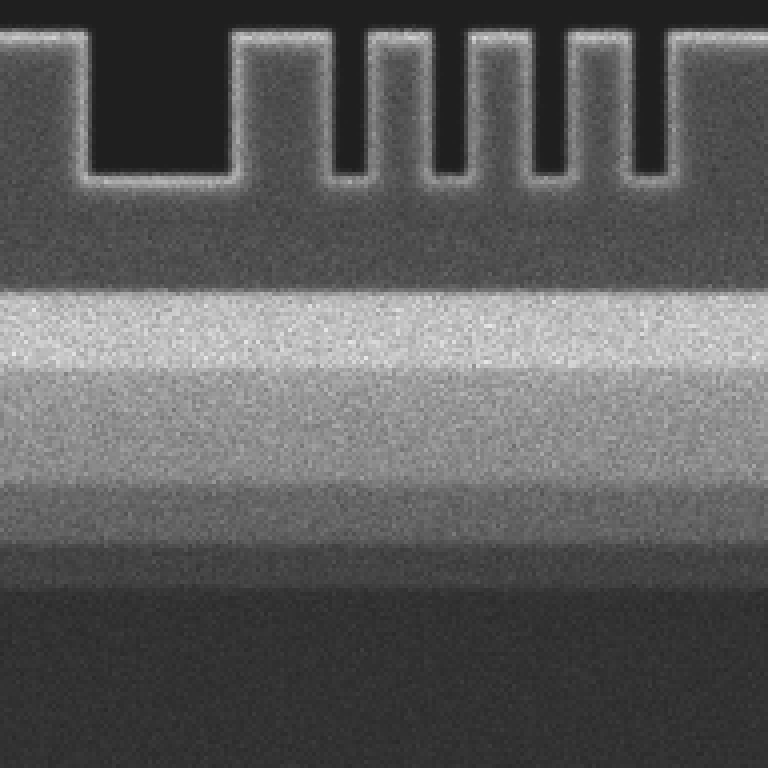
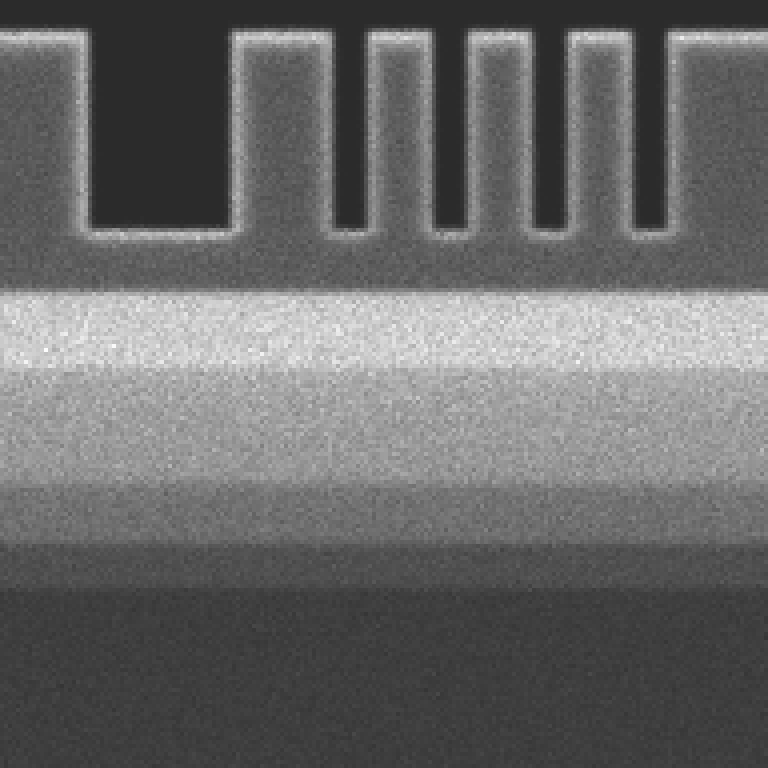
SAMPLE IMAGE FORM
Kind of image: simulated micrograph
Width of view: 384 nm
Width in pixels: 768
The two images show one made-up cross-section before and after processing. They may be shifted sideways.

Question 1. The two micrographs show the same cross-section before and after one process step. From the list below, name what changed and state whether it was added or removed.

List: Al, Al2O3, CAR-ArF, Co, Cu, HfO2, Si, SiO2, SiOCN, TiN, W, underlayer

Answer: underlayer, removed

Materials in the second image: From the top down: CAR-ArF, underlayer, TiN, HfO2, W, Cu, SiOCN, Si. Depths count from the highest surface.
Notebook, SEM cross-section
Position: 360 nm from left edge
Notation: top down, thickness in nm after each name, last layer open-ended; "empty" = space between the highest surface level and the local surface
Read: CAR-ArF 72, underlayer 28, TiN 30, HfO2 38, W 58, Cu 30, SiOCN 22, Si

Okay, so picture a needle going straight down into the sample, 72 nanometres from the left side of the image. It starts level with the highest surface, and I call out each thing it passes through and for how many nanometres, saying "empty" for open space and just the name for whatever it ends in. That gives empty 100, TiN 30, HfO2 38, W 58, Cu 30, SiOCN 22, Si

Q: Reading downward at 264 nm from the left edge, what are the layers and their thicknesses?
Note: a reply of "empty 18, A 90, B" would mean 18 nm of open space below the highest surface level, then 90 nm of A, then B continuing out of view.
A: CAR-ArF 72, underlayer 28, TiN 30, HfO2 38, W 58, Cu 30, SiOCN 22, Si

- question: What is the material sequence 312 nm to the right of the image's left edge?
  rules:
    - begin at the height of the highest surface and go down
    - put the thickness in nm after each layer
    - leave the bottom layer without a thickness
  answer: CAR-ArF 72, underlayer 28, TiN 30, HfO2 38, W 58, Cu 30, SiOCN 22, Si